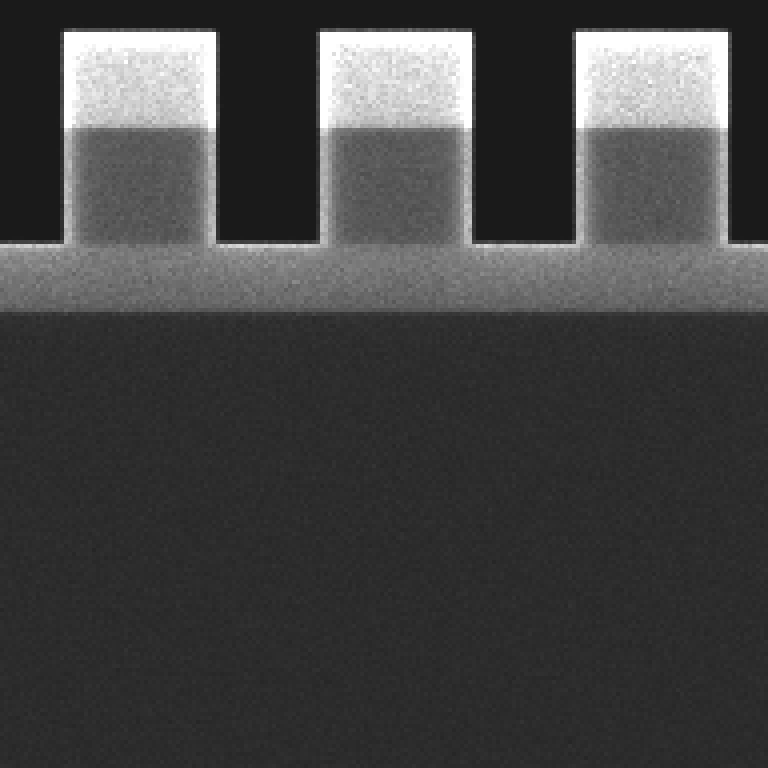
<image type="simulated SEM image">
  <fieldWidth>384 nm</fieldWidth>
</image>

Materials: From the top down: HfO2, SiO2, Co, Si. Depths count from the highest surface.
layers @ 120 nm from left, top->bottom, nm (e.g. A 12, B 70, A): empty 106, Co 34, Si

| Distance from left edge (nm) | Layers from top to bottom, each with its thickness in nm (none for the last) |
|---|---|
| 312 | HfO2 48, SiO2 58, Co 34, Si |